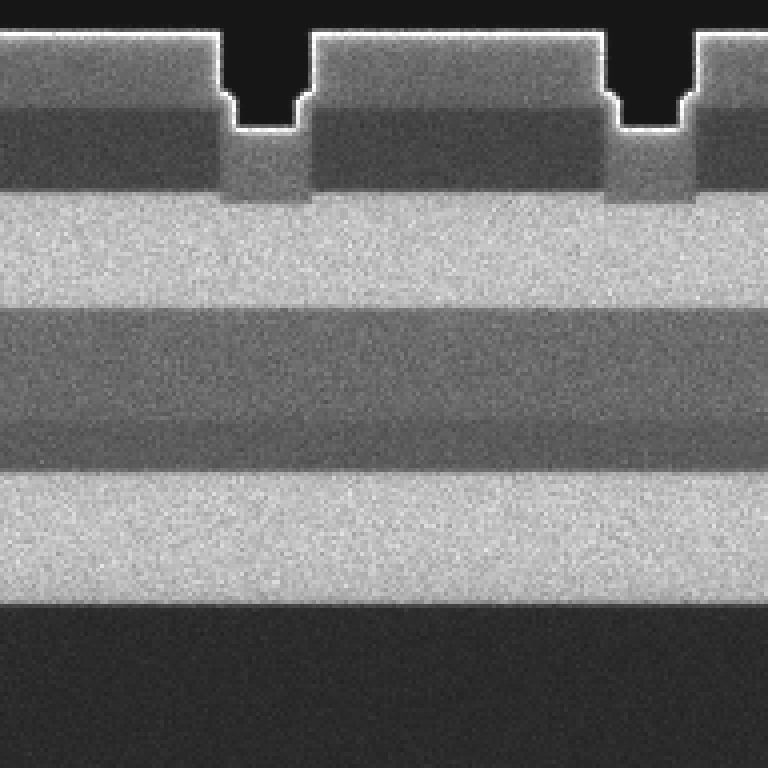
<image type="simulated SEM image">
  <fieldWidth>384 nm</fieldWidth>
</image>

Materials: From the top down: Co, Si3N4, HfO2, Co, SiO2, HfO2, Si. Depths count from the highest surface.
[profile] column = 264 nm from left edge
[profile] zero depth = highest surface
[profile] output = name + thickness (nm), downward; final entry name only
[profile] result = Co 38, Si3N4 42, HfO2 58, Co 56, SiO2 26, HfO2 66, Si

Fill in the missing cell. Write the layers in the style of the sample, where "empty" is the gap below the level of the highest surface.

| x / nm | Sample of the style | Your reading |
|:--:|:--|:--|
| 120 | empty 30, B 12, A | empty 48, Co 38, HfO2 52, Co 56, SiO2 26, HfO2 66, Si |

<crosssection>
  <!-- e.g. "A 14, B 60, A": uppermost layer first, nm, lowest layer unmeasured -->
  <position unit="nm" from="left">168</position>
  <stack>Co 38, Si3N4 42, HfO2 58, Co 56, SiO2 26, HfO2 66, Si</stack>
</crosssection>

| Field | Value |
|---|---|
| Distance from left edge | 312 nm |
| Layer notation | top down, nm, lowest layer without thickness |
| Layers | empty 48, Co 38, HfO2 52, Co 56, SiO2 26, HfO2 66, Si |